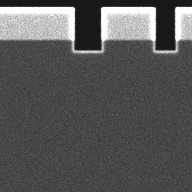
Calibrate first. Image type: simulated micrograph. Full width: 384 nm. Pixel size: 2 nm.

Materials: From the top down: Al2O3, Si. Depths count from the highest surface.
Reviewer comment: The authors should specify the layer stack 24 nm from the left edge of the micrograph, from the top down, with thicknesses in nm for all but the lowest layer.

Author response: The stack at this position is Al2O3 64, Si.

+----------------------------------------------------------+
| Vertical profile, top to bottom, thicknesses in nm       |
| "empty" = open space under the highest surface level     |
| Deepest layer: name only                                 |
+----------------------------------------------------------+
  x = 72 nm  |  Al2O3 64, Si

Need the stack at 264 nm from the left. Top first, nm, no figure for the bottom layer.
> Al2O3 64, Si